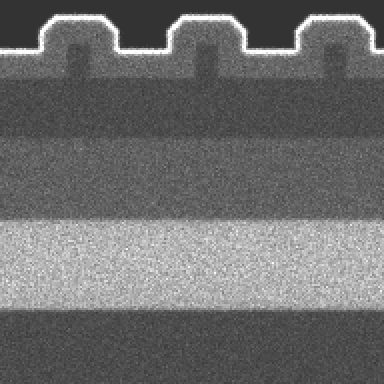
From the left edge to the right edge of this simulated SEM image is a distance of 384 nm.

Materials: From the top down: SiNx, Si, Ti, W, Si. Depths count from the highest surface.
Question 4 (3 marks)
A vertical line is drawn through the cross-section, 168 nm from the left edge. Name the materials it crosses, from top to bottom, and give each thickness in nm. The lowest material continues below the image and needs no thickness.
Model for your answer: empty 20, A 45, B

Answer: empty 14, SiNx 48, Si 60, Ti 82, W 90, Si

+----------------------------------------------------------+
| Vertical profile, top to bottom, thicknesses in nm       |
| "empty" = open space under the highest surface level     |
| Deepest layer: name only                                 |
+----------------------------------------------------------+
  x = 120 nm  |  empty 34, SiNx 28, Si 60, Ti 82, W 90, Si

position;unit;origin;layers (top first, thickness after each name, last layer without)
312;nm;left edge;SiNx 62, Si 60, Ti 82, W 90, Si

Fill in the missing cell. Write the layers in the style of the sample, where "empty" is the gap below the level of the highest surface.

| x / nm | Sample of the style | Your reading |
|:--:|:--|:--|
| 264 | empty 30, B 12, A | empty 34, SiNx 28, Si 60, Ti 82, W 90, Si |